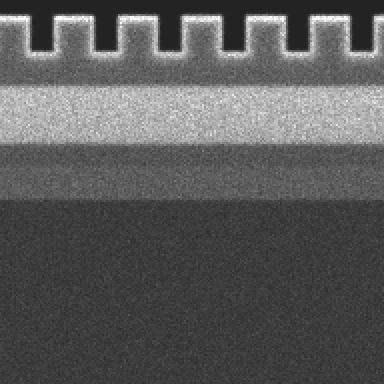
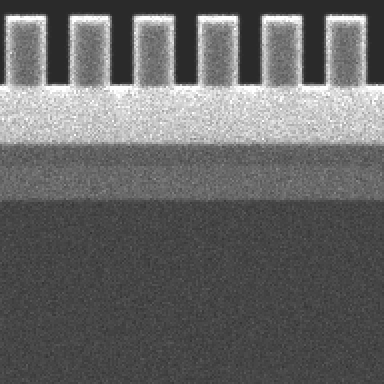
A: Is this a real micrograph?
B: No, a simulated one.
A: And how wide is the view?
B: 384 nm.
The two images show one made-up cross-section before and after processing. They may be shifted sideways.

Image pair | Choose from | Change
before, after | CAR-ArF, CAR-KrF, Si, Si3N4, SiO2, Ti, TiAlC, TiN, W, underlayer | underlayer (removed)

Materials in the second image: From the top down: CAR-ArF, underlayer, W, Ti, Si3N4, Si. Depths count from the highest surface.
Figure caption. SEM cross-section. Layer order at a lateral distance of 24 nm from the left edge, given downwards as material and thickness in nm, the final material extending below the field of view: CAR-ArF 36, underlayer 34, W 58, Ti 22, Si3N4 34, Si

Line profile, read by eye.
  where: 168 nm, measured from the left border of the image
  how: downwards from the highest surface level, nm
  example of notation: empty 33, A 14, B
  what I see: CAR-ArF 36, underlayer 34, W 58, Ti 22, Si3N4 34, Si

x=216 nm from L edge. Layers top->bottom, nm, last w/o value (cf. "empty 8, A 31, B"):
CAR-ArF 36, underlayer 34, W 58, Ti 22, Si3N4 34, Si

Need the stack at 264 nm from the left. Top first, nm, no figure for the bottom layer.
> CAR-ArF 36, underlayer 34, W 58, Ti 22, Si3N4 34, Si